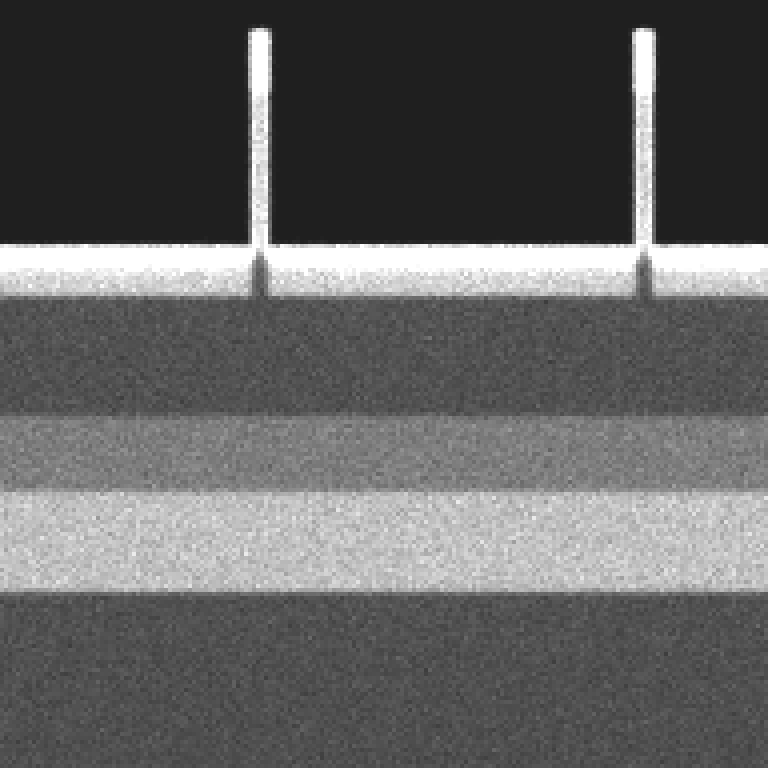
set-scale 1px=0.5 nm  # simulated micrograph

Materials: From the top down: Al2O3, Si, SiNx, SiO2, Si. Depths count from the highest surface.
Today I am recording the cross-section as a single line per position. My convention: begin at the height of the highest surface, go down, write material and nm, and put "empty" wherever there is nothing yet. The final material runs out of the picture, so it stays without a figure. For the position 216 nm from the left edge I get empty 108, Al2O3 24, Si 60, SiNx 38, SiO2 50, Si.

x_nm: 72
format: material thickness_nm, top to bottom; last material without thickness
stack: empty 108, Al2O3 24, Si 60, SiNx 38, SiO2 50, Si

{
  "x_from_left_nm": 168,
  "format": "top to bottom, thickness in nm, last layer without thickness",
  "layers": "empty 108, Al2O3 24, Si 60, SiNx 38, SiO2 50, Si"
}